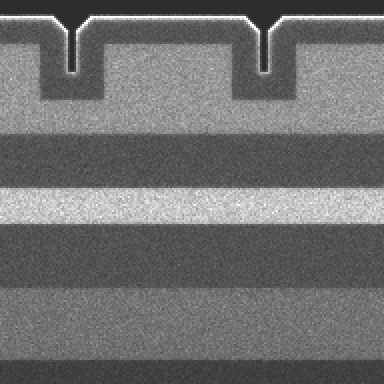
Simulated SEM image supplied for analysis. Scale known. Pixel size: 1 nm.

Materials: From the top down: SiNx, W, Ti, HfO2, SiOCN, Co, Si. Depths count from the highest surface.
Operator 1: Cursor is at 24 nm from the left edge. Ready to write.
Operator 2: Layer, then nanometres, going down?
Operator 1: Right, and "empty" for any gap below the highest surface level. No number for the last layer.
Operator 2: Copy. SiNx 28, W 90, Ti 54, HfO2 36, SiOCN 64, Co 72, Si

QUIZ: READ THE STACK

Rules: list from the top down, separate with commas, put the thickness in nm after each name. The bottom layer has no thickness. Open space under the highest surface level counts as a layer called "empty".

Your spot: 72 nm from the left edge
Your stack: empty 56, SiNx 28, W 34, Ti 54, HfO2 36, SiOCN 64, Co 72, Si